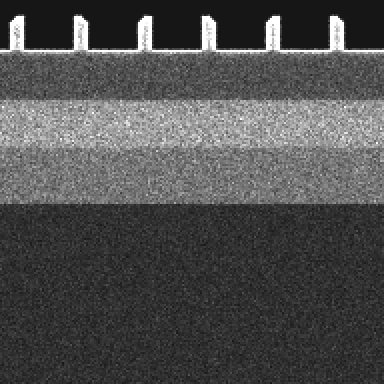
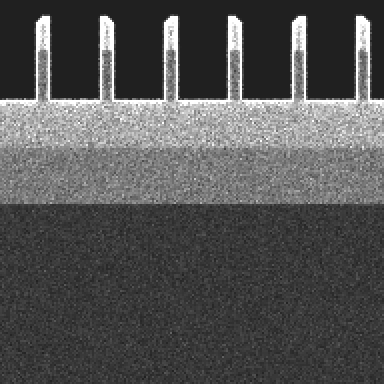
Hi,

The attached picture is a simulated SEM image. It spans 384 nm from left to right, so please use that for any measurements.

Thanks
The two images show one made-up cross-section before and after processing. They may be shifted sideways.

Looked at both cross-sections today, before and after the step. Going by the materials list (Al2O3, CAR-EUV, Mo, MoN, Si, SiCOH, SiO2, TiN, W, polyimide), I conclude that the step removed TiN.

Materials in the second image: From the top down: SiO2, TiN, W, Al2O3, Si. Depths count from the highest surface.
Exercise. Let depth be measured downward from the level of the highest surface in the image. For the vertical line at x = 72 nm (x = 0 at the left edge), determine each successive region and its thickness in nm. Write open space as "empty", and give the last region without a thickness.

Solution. empty 84, W 48, Al2O3 56, Si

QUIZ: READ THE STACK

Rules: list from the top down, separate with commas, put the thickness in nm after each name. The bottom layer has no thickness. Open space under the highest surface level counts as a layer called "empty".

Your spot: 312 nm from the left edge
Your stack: empty 84, W 48, Al2O3 56, Si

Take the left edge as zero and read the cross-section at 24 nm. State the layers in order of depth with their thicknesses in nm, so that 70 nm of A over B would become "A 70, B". empty 84, W 48, Al2O3 56, Si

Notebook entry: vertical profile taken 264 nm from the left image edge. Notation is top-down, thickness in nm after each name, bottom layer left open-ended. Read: empty 84, W 48, Al2O3 56, Si